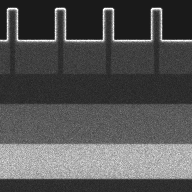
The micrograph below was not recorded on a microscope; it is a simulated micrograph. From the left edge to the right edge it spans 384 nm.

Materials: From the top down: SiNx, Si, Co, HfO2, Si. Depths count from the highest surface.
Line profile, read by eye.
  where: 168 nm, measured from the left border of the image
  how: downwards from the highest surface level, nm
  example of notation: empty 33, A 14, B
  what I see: empty 64, SiNx 68, Si 60, Co 80, HfO2 70, Si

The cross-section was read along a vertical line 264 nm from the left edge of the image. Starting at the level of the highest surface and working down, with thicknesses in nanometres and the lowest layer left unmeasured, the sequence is empty 64, SiNx 68, Si 60, Co 80, HfO2 70, Si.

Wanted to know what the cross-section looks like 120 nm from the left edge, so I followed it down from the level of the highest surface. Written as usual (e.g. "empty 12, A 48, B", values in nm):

SiNx 6, Si 186, Co 80, HfO2 70, Si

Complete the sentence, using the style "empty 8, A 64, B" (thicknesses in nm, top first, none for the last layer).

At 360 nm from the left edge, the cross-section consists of empty 64, SiNx 68, Si 60, Co 80, HfO2 70, Si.